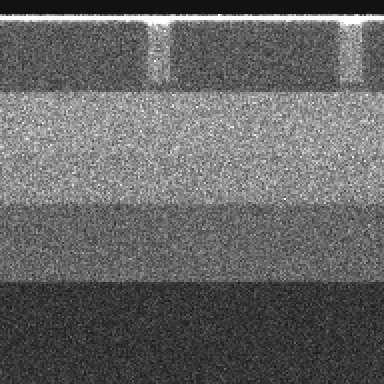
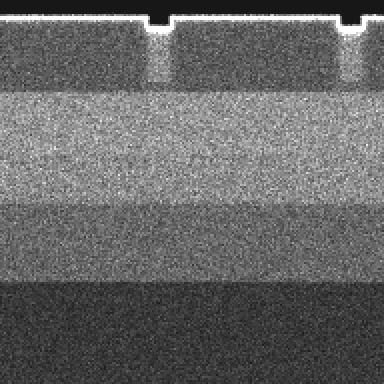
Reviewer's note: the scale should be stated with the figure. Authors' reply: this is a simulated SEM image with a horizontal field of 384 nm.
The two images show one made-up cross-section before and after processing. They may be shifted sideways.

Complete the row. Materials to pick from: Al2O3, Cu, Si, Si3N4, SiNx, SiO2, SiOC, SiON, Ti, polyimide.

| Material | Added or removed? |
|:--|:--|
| SiO2 | removed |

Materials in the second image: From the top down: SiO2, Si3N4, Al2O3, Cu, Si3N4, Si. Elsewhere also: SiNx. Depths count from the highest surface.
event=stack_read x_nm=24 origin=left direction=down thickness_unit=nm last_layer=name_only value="SiNx 76, Al2O3 62, Cu 50, Si3N4 78, Si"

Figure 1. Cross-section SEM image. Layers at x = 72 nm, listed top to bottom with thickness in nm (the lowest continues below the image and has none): SiNx 76, Al2O3 62, Cu 50, Si3N4 78, Si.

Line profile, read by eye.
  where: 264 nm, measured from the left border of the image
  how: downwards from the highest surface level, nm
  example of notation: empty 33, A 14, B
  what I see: SiNx 76, Al2O3 62, Cu 50, Si3N4 78, Si